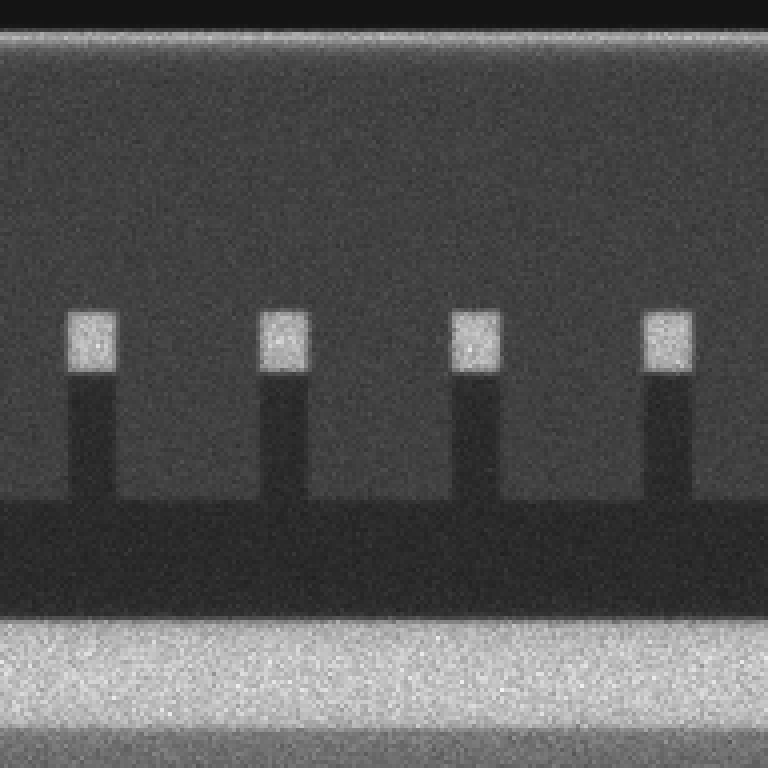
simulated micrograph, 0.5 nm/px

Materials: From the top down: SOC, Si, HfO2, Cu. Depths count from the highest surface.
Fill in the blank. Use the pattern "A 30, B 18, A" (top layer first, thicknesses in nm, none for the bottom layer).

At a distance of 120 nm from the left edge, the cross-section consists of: SOC 234, Si 60, HfO2 54, Cu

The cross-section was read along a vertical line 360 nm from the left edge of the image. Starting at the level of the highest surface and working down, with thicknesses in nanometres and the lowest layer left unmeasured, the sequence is SOC 234, Si 60, HfO2 54, Cu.